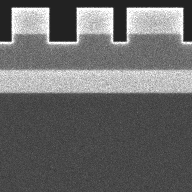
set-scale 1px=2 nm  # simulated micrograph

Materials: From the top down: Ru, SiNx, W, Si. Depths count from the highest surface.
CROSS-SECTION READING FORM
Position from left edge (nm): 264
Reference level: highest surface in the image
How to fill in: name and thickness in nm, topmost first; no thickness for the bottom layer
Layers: Ru 52, SiNx 72, W 46, Si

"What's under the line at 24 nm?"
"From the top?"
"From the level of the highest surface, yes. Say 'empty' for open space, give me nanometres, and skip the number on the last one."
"Ru 52, SiNx 72, W 46, Si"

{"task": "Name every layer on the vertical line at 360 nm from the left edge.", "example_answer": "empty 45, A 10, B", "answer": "Ru 52, SiNx 72, W 46, Si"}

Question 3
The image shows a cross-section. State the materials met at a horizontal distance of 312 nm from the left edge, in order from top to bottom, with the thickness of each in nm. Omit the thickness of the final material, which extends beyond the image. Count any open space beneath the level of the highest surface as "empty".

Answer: Ru 52, SiNx 72, W 46, Si